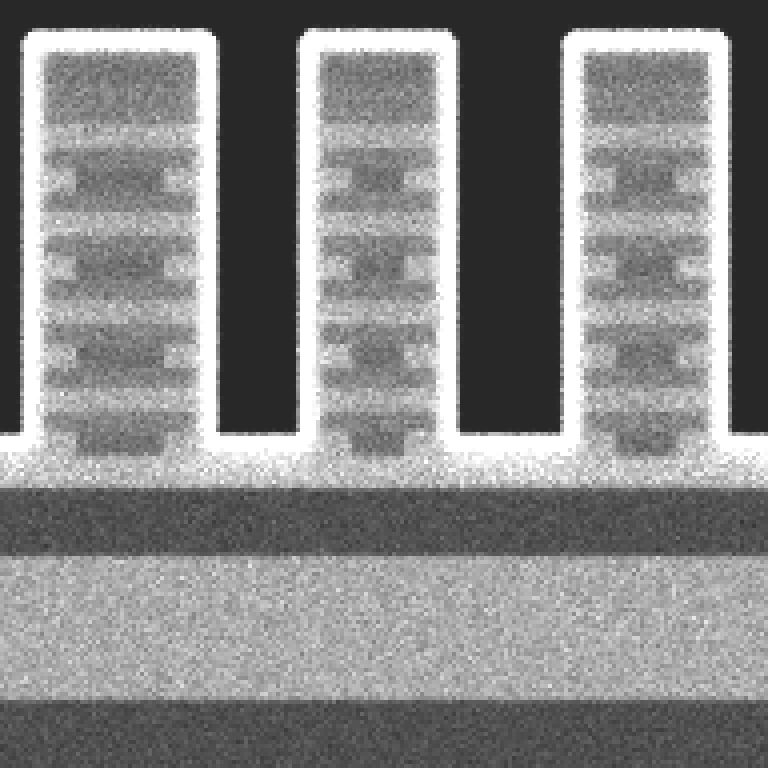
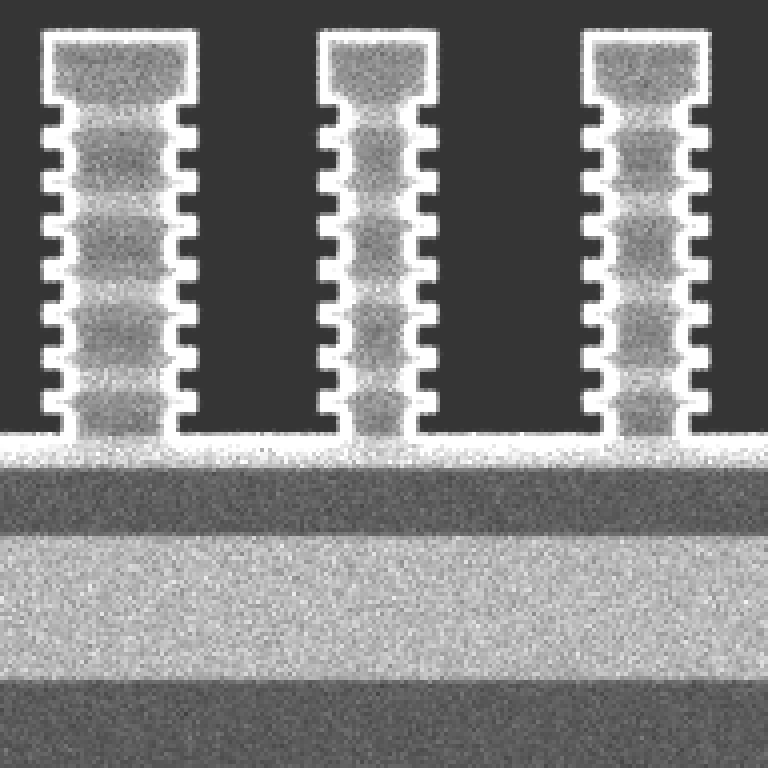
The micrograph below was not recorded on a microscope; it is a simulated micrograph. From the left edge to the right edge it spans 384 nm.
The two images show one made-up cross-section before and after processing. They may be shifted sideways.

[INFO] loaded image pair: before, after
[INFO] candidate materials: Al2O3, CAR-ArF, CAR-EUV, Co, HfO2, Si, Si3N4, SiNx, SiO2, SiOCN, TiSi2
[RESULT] removed Al2O3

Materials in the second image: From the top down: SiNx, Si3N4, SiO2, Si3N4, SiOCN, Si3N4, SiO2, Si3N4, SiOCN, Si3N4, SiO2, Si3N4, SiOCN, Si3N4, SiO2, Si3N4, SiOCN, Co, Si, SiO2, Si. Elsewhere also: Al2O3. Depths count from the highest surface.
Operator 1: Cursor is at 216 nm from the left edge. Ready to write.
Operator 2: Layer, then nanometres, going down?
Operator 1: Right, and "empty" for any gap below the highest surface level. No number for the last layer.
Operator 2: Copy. SiNx 16, Si3N4 20, empty 12, Si3N4 10, empty 12, Si3N4 10, empty 12, Si3N4 10, empty 12, Si3N4 10, empty 12, Si3N4 10, empty 12, Si3N4 10, empty 12, Si3N4 10, empty 12, Co 16, Si 34, SiO2 72, Si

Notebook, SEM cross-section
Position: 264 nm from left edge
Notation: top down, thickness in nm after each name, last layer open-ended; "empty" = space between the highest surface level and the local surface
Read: empty 202, Co 16, Si 34, SiO2 72, Si